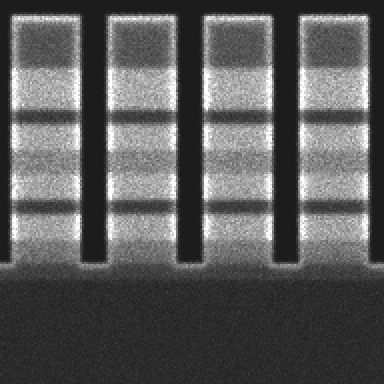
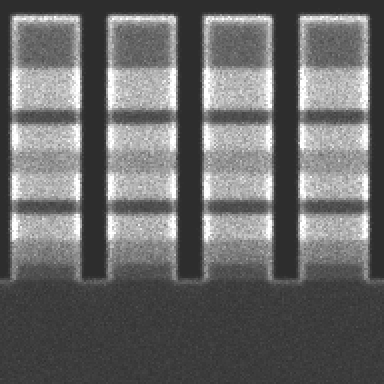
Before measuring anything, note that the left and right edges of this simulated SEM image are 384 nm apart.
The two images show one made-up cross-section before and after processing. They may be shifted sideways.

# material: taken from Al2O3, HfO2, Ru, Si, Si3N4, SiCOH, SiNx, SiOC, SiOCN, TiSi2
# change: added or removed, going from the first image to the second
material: Si3N4
change: removed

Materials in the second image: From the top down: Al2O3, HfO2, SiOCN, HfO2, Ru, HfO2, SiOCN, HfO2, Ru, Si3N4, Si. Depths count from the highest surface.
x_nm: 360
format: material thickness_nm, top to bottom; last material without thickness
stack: Al2O3 52, HfO2 42, SiOCN 14, HfO2 26, Ru 24, HfO2 26, SiOCN 14, HfO2 26, Ru 24, Si3N4 16, Si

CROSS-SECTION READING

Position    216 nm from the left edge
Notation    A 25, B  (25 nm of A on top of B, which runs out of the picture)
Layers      Al2O3 52, HfO2 42, SiOCN 14, HfO2 26, Ru 24, HfO2 26, SiOCN 14, HfO2 26, Ru 24, Si3N4 16, Si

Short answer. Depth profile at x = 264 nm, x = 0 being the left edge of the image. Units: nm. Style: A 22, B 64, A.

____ Al2O3 52, HfO2 42, SiOCN 14, HfO2 26, Ru 24, HfO2 26, SiOCN 14, HfO2 26, Ru 24, Si3N4 16, Si